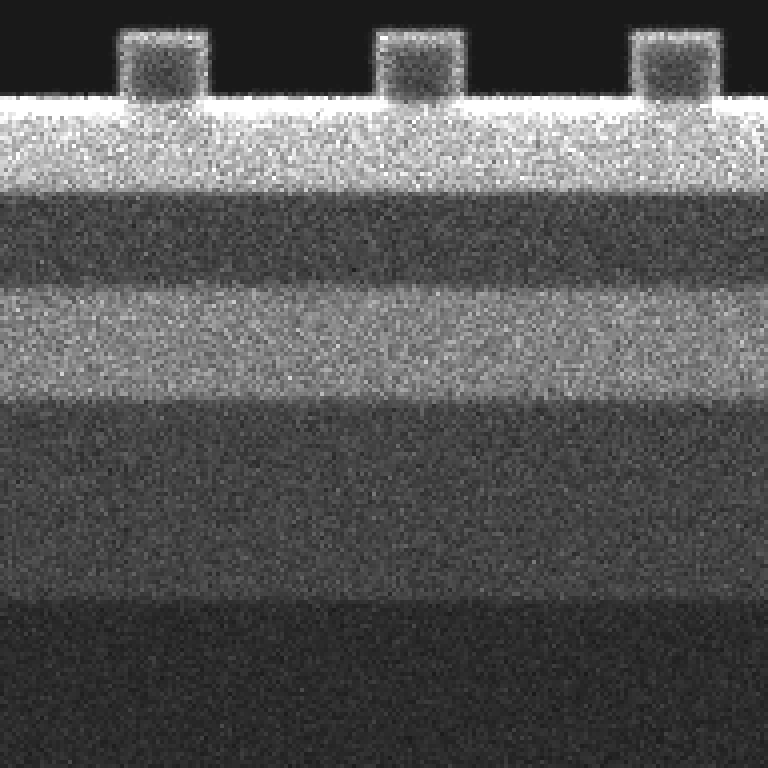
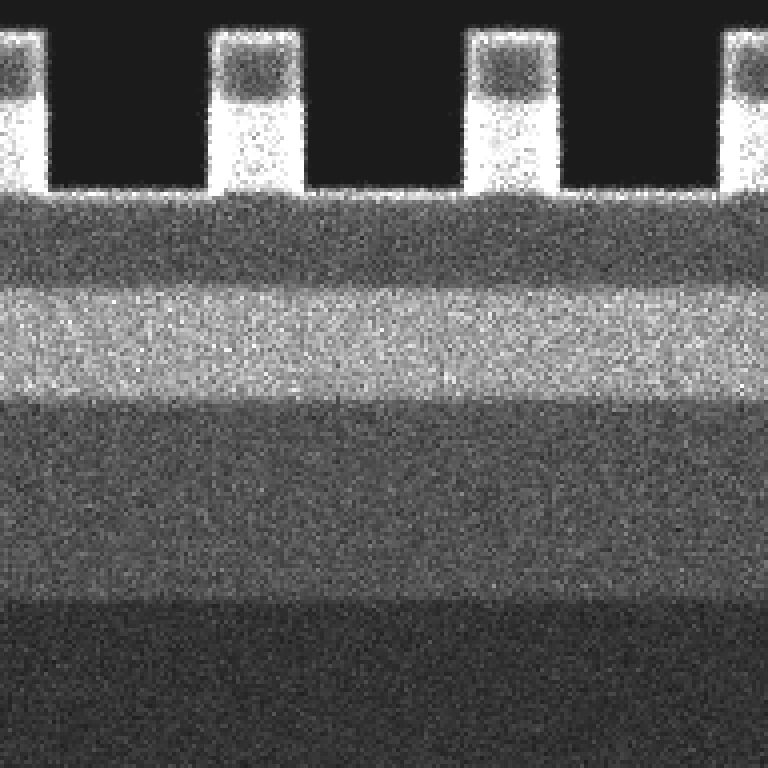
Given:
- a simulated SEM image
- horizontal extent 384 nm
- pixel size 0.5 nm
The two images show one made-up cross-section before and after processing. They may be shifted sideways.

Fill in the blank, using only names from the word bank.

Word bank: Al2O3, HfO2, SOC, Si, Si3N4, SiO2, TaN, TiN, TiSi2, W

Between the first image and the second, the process removed HfO2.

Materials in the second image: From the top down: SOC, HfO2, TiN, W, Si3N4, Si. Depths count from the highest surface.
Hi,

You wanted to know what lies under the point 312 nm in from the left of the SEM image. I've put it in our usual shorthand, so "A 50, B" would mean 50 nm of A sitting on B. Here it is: empty 80, TiN 48, W 56, Si3N4 100, Si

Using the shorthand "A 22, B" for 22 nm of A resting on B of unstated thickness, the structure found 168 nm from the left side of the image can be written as empty 80, TiN 48, W 56, Si3N4 100, Si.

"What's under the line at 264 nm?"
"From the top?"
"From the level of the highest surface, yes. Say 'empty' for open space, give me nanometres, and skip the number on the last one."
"SOC 34, HfO2 46, TiN 48, W 56, Si3N4 100, Si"